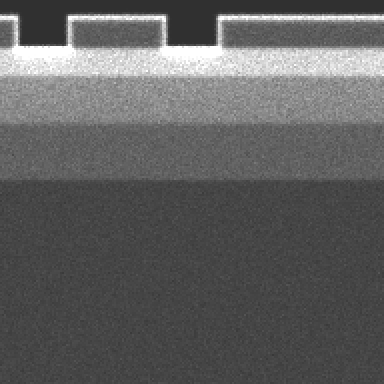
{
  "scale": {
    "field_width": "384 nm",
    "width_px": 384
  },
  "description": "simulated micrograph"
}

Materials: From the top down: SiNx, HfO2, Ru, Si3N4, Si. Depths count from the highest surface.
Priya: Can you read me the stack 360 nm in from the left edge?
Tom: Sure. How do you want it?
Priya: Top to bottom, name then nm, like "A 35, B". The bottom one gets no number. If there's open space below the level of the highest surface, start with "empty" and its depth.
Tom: SiNx 32, HfO2 28, Ru 48, Si3N4 56, Si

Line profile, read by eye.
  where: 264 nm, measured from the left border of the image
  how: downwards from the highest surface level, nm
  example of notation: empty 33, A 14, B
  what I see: SiNx 32, HfO2 28, Ru 48, Si3N4 56, Si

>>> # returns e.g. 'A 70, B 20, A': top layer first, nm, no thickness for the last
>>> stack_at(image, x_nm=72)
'SiNx 32, HfO2 28, Ru 48, Si3N4 56, Si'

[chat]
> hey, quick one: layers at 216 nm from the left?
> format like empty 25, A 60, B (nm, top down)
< empty 32, HfO2 28, Ru 48, Si3N4 56, Si